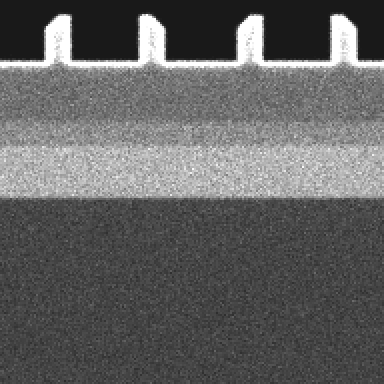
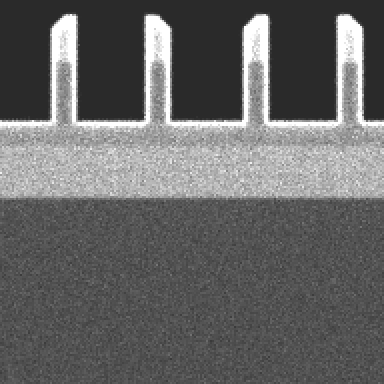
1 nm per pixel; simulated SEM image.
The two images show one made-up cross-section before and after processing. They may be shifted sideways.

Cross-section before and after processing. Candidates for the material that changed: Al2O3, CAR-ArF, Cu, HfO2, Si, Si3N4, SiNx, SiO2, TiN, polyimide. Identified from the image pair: SiNx (removed).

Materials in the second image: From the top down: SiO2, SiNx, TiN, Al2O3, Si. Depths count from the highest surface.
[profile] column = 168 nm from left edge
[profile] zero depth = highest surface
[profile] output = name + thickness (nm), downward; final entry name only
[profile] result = empty 12, SiO2 34, SiNx 60, TiN 24, Al2O3 52, Si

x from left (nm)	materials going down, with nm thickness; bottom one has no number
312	empty 106, TiN 24, Al2O3 52, Si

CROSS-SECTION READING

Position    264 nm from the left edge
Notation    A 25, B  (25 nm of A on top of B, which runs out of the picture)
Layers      SiO2 46, SiNx 60, TiN 24, Al2O3 52, Si